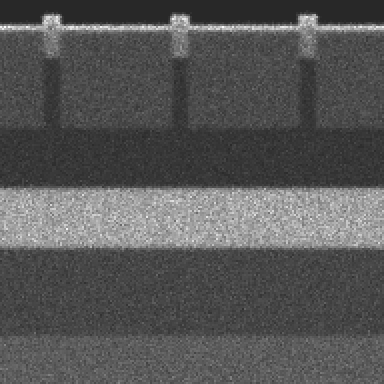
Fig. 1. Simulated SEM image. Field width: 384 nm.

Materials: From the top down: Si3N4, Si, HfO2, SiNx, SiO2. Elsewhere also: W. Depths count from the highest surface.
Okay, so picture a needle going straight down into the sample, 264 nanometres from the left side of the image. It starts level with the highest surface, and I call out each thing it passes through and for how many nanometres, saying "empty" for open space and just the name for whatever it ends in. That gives empty 10, Si3N4 102, Si 60, HfO2 60, SiNx 88, SiO2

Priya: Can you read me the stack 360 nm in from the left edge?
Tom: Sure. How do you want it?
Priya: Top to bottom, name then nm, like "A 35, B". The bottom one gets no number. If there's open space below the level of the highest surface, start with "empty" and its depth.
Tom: empty 10, Si3N4 102, Si 60, HfO2 60, SiNx 88, SiO2